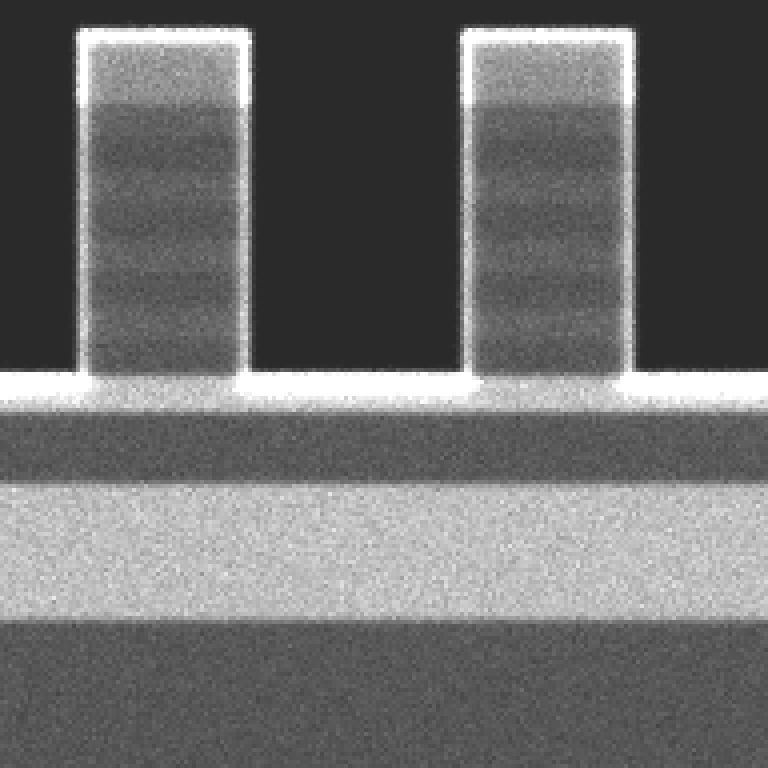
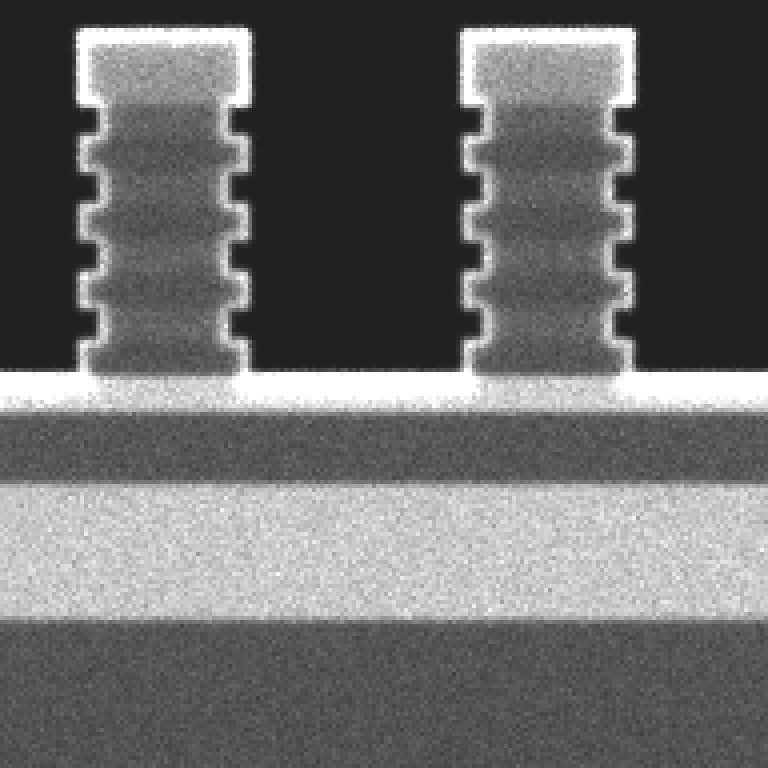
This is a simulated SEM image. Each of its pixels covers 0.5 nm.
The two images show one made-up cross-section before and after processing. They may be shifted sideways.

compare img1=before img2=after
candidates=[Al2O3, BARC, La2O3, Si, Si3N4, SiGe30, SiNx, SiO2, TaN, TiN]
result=removed:SiGe30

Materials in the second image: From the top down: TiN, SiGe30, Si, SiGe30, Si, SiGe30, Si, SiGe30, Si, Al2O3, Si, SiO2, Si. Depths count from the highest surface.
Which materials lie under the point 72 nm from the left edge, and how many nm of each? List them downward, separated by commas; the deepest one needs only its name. TiN 36, SiGe30 16, Si 18, SiGe30 16, Si 18, SiGe30 16, Si 18, SiGe30 16, Si 18, Al2O3 18, Si 36, SiO2 68, Si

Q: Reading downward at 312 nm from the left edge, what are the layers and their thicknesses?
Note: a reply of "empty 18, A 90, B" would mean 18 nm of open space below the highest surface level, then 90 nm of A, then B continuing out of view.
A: TiN 36, empty 16, Si 18, empty 16, Si 18, empty 16, Si 18, empty 16, Si 18, Al2O3 18, Si 36, SiO2 68, Si